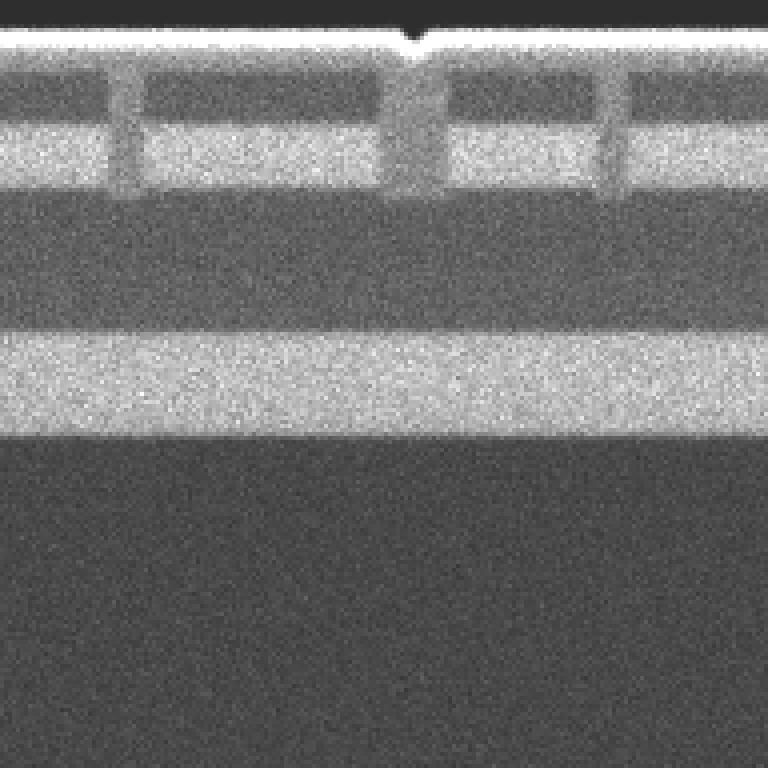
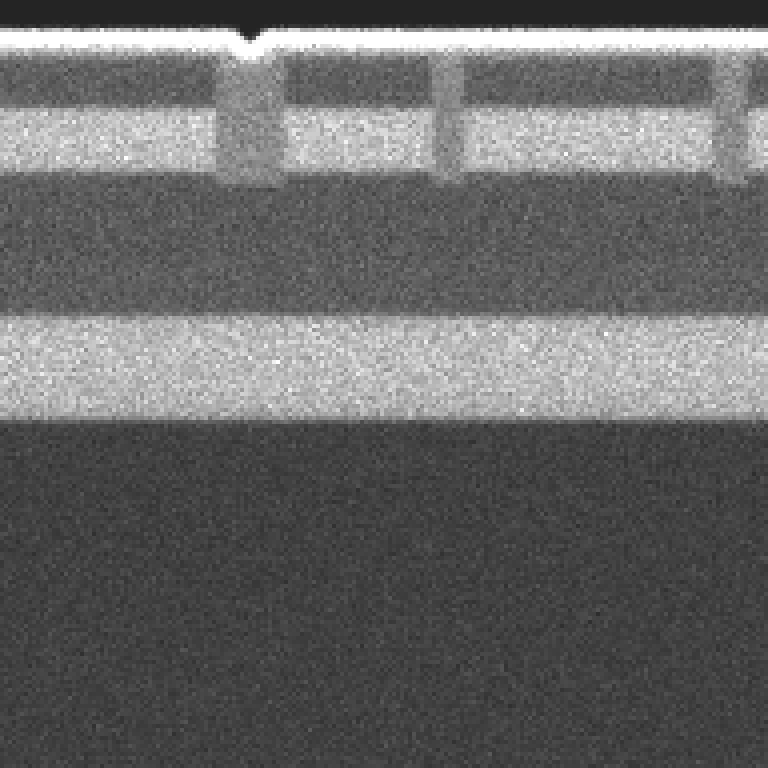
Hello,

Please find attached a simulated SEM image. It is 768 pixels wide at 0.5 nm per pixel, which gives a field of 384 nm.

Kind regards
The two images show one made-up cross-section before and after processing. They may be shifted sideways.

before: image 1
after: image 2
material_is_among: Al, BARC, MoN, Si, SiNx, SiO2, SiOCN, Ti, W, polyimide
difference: SiO2, removed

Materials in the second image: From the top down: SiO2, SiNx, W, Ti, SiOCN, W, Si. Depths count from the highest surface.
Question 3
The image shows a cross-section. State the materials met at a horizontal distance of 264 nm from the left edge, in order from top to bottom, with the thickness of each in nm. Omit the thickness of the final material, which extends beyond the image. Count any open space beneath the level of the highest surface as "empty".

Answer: SiO2 12, SiNx 26, W 32, Ti 42, SiOCN 30, W 52, Si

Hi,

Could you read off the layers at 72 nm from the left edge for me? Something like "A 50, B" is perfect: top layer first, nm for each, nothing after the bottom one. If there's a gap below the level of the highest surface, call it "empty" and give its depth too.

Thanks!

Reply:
SiO2 12, SiNx 26, W 32, Ti 42, SiOCN 30, W 52, Si